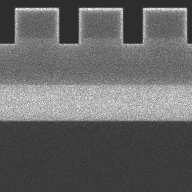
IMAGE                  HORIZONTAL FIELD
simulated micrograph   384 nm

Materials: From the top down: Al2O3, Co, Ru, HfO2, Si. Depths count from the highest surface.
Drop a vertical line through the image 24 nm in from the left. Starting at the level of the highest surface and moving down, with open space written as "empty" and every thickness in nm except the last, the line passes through empty 72, Co 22, Ru 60, HfO2 72, Si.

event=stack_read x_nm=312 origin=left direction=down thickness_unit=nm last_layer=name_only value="Al2O3 60, Co 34, Ru 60, HfO2 72, Si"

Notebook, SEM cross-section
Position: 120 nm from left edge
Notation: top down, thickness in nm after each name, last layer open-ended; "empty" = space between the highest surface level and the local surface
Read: empty 72, Co 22, Ru 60, HfO2 72, Si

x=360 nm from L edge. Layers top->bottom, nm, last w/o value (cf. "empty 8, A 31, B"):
Al2O3 60, Co 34, Ru 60, HfO2 72, Si